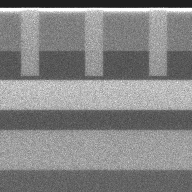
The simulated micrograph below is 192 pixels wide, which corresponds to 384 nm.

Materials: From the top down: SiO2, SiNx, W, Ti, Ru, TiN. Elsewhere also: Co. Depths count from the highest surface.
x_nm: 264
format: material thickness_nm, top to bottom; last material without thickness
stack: SiO2 86, SiNx 58, W 60, Ti 40, Ru 80, TiN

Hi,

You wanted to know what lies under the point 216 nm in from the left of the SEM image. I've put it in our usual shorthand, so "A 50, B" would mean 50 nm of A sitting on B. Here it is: SiO2 86, SiNx 58, W 60, Ti 40, Ru 80, TiN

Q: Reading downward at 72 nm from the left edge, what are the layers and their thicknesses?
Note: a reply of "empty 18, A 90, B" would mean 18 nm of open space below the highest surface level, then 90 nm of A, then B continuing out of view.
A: Co 136, SiNx 8, W 60, Ti 40, Ru 80, TiN